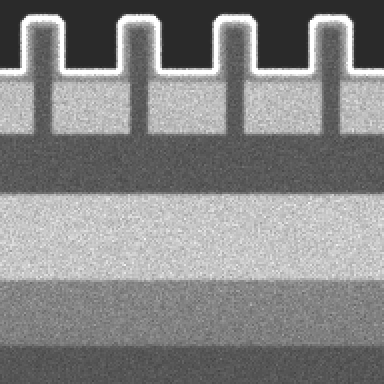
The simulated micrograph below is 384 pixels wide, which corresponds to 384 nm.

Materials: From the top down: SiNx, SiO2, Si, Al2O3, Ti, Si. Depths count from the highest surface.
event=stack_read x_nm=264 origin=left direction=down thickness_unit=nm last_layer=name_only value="empty 54, SiNx 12, SiO2 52, Si 60, Al2O3 86, Ti 66, Si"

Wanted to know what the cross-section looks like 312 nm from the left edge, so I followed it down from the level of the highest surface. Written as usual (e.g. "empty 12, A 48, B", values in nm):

empty 4, SiNx 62, SiO2 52, Si 60, Al2O3 86, Ti 66, Si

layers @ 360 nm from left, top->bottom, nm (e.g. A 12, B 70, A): empty 54, SiNx 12, SiO2 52, Si 60, Al2O3 86, Ti 66, Si